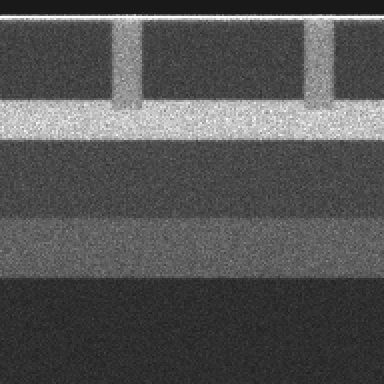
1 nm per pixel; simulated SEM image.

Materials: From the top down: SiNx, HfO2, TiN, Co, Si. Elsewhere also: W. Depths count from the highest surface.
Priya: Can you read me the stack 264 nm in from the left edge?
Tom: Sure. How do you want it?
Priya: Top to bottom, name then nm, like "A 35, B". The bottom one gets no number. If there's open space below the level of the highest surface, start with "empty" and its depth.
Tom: SiNx 84, HfO2 40, TiN 78, Co 60, Si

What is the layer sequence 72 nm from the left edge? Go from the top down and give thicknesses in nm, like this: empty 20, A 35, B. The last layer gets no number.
SiNx 84, HfO2 40, TiN 78, Co 60, Si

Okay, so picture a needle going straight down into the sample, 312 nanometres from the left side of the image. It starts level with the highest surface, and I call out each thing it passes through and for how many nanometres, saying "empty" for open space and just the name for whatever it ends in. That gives W 94, HfO2 30, TiN 78, Co 60, Si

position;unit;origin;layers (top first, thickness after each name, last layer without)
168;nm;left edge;SiNx 84, HfO2 40, TiN 78, Co 60, Si